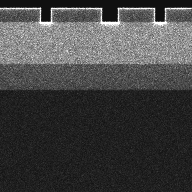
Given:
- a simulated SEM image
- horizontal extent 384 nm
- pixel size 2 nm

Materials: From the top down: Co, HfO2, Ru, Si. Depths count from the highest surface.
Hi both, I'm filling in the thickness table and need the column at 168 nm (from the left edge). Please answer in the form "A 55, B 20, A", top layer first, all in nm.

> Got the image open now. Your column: Co 28, HfO2 84, Ru 52, Si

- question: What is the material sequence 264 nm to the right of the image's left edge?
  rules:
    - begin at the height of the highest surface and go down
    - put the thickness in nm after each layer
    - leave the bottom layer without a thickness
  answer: Co 28, HfO2 84, Ru 52, Si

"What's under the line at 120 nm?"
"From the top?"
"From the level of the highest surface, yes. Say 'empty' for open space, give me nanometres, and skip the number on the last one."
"Co 28, HfO2 84, Ru 52, Si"